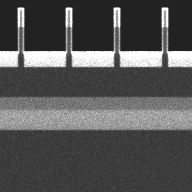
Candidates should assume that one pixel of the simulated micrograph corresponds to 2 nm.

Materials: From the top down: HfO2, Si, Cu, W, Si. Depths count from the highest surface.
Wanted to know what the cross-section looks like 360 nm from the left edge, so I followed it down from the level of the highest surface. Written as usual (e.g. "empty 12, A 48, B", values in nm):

empty 88, HfO2 30, Si 60, Cu 26, W 40, Si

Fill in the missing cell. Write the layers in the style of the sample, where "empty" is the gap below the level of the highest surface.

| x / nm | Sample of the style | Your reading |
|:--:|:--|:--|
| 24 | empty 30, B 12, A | empty 88, HfO2 30, Si 60, Cu 26, W 40, Si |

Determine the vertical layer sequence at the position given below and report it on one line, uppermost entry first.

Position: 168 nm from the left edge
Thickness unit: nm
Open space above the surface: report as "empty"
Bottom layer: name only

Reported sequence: empty 88, HfO2 30, Si 60, Cu 26, W 40, Si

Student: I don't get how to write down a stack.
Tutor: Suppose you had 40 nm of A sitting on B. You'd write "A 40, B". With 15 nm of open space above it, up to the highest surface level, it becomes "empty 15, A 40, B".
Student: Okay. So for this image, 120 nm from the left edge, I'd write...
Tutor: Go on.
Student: empty 88, HfO2 30, Si 60, Cu 26, W 40, Si